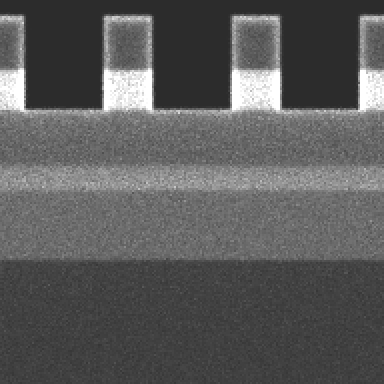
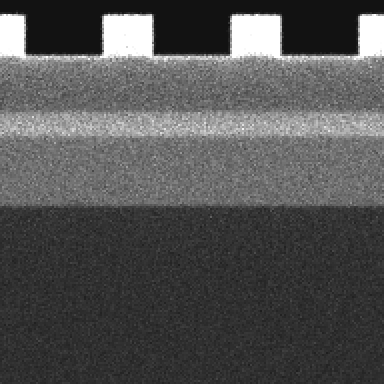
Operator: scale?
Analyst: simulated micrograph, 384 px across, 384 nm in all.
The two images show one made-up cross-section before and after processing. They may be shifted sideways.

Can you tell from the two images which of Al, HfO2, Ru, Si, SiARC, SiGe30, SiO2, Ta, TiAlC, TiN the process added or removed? Yes, it removed SiARC.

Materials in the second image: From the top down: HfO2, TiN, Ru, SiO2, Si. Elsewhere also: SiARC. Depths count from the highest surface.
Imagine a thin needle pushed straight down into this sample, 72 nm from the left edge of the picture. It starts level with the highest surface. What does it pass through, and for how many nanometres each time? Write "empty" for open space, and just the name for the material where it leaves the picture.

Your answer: empty 40, TiN 56, Ru 24, SiO2 70, Si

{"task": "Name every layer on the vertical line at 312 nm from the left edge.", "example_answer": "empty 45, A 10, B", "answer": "empty 40, TiN 56, Ru 24, SiO2 70, Si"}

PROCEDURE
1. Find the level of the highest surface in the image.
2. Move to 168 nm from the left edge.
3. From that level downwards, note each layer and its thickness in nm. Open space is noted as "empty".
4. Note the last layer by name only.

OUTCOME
empty 40, TiN 56, Ru 24, SiO2 70, Si